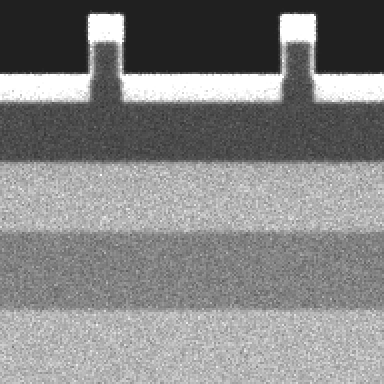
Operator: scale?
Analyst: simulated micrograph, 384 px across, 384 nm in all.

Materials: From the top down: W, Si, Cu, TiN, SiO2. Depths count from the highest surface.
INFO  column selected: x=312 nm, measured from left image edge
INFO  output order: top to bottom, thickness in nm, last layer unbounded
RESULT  W 26, Si 120, Cu 70, TiN 78, SiO2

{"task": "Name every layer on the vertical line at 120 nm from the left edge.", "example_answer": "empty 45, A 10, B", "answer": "W 26, Si 120, Cu 70, TiN 78, SiO2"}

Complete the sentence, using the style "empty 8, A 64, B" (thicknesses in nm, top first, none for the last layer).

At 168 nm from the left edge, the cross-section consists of empty 60, W 26, Si 60, Cu 70, TiN 78, SiO2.